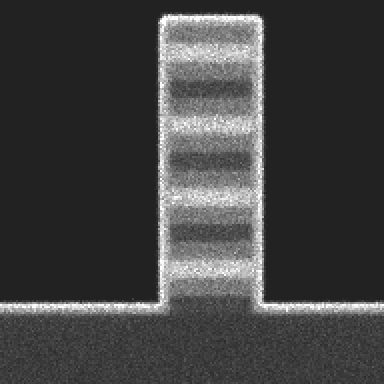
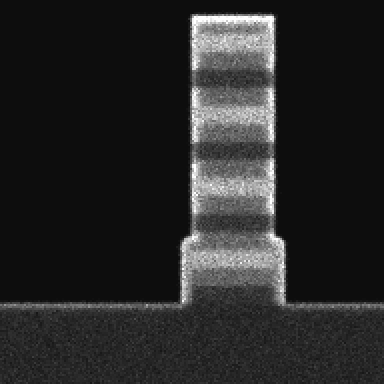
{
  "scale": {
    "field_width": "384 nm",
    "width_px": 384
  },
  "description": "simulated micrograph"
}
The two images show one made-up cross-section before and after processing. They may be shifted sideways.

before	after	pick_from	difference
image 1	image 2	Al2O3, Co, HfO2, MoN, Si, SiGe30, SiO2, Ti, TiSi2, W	Co removed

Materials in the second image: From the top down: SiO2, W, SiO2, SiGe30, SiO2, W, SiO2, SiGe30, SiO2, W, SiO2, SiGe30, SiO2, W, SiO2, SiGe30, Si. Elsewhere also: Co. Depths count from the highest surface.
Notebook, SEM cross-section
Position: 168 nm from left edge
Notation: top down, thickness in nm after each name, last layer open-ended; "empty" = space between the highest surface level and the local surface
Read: empty 288, Si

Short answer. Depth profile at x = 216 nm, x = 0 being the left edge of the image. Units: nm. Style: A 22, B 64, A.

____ SiO2 18, W 18, SiO2 18, SiGe30 18, SiO2 18, W 18, SiO2 18, SiGe30 18, SiO2 18, W 18, SiO2 18, SiGe30 18, SiO2 18, W 18, SiO2 18, SiGe30 18, Si